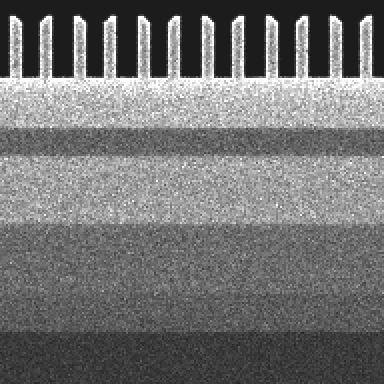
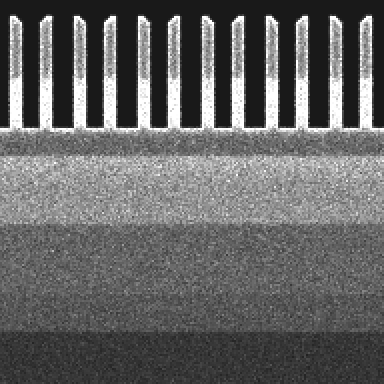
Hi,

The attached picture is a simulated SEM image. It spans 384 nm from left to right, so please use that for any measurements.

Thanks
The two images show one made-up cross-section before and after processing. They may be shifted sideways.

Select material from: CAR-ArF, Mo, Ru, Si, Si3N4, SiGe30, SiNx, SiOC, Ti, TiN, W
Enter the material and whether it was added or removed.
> W / removed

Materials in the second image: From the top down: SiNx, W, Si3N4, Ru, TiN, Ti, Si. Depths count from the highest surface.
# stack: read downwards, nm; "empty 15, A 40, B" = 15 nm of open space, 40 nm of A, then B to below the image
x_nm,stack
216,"empty 112, Si3N4 28, Ru 68, TiN 70, Ti 38, Si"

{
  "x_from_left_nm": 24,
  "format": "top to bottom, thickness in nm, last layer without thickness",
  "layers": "empty 112, Si3N4 28, Ru 68, TiN 70, Ti 38, Si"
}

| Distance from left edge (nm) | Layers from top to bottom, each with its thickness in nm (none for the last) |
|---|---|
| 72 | empty 112, Si3N4 28, Ru 68, TiN 70, Ti 38, Si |